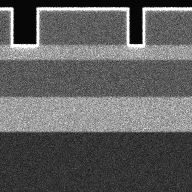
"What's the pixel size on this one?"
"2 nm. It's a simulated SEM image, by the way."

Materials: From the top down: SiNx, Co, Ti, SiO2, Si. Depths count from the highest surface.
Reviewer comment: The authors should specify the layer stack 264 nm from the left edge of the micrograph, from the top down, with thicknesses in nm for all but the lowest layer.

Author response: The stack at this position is empty 74, Co 30, Ti 74, SiO2 70, Si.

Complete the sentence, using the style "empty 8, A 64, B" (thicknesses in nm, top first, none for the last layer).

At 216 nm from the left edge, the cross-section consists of SiNx 74, Co 30, Ti 74, SiO2 70, Si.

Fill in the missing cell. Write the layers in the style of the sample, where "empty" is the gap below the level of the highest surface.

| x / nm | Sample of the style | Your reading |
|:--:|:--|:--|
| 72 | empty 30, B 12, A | empty 74, Co 30, Ti 74, SiO2 70, Si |